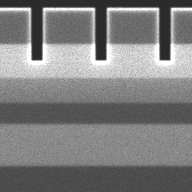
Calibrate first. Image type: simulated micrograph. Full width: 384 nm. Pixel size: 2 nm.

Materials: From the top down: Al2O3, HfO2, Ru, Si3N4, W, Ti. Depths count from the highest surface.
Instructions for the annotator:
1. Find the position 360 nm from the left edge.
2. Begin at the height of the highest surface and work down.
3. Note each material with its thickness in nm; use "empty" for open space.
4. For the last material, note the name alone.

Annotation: Al2O3 72, HfO2 68, Ru 50, Si3N4 42, W 84, Ti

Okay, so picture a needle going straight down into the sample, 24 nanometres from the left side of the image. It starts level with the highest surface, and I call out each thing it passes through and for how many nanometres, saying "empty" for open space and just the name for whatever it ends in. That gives Al2O3 72, HfO2 68, Ru 50, Si3N4 42, W 84, Ti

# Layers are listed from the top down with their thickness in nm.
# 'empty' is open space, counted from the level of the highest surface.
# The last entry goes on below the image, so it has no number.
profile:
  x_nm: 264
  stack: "Al2O3 72, HfO2 68, Ru 50, Si3N4 42, W 84, Ti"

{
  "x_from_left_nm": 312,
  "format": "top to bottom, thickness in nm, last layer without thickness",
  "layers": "Al2O3 72, HfO2 68, Ru 50, Si3N4 42, W 84, Ti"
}